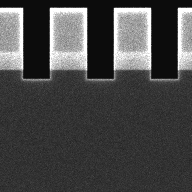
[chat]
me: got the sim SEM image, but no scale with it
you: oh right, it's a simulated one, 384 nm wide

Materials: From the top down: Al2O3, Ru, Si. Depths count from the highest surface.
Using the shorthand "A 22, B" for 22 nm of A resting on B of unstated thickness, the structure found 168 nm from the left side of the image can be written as Al2O3 88, Ru 36, Si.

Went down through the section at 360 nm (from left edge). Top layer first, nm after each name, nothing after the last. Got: Al2O3 88, Ru 36, Si